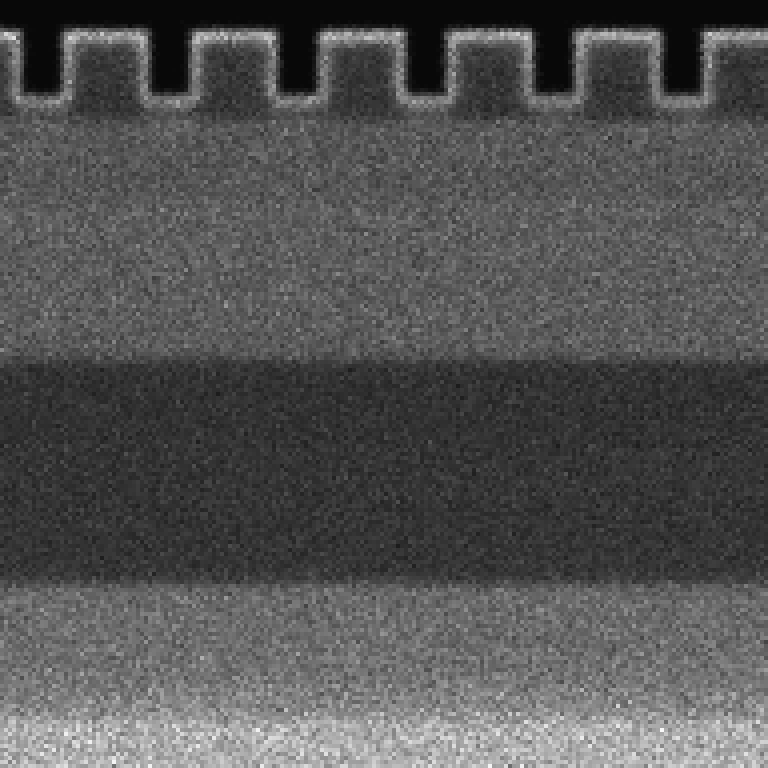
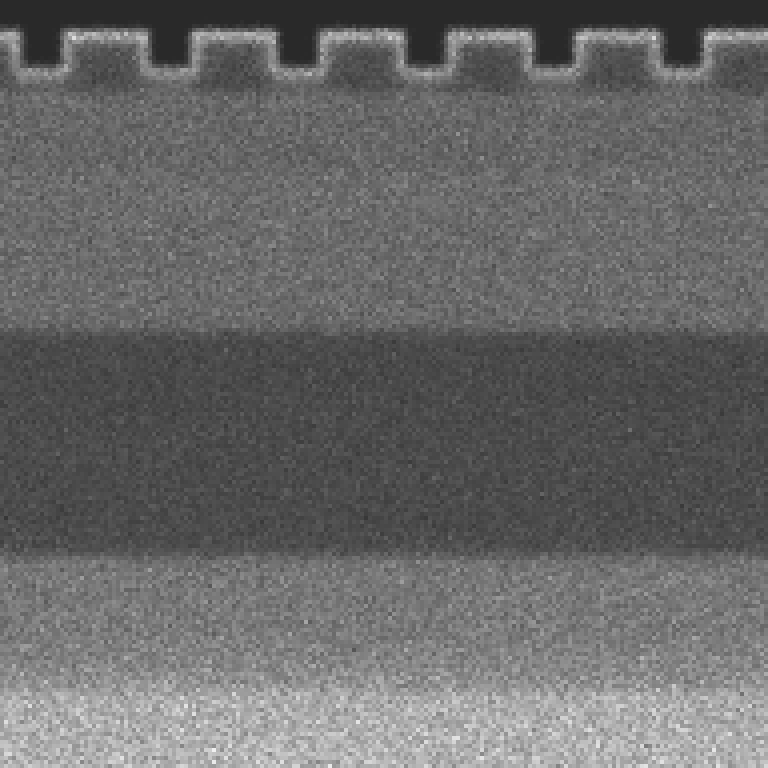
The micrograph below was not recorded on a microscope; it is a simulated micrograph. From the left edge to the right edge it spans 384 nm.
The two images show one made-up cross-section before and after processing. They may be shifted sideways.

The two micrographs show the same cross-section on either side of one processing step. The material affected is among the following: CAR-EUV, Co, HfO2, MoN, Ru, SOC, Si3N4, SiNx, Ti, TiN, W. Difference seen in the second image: Si3N4 removed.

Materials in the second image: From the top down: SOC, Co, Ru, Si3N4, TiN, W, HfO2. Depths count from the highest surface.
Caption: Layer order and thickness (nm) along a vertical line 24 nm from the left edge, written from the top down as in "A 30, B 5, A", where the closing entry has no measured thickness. empty 18, SOC 12, Co 40, Ru 80, Si3N4 40, TiN 72, W 68, HfO2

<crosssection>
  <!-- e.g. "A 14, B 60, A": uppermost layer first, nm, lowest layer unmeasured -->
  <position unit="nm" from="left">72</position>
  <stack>Si3N4 30, Co 40, Ru 80, Si3N4 40, TiN 72, W 68, HfO2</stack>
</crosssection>